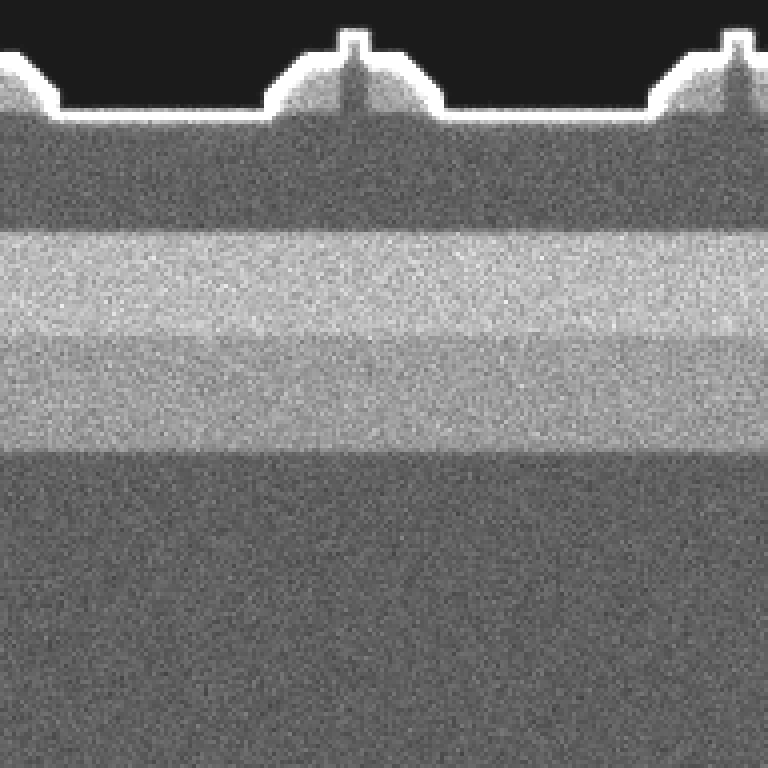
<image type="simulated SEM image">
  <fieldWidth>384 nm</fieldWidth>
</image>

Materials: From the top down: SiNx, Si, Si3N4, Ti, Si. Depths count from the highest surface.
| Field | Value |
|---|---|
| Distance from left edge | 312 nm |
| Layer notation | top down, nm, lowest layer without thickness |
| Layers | empty 40, Si 60, Si3N4 52, Ti 58, Si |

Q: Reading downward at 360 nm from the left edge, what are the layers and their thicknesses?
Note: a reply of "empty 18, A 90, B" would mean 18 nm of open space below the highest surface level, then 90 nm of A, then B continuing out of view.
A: empty 12, SiNx 28, Si 60, Si3N4 52, Ti 58, Si